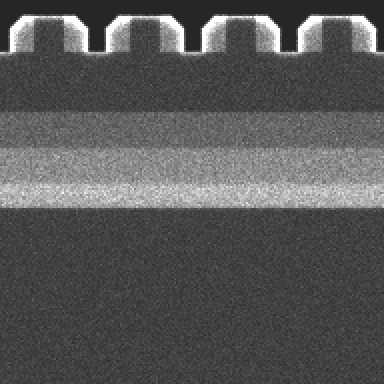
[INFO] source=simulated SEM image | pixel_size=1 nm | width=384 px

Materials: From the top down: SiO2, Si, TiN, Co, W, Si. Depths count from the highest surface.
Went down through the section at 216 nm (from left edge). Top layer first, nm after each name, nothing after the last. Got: SiO2 36, Si 60, TiN 36, Co 36, W 24, Si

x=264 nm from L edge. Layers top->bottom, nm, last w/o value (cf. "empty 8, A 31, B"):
SiO2 36, Si 60, TiN 36, Co 36, W 24, Si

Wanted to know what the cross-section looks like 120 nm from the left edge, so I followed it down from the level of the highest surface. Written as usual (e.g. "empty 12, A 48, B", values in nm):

SiO2 36, Si 60, TiN 36, Co 36, W 24, Si